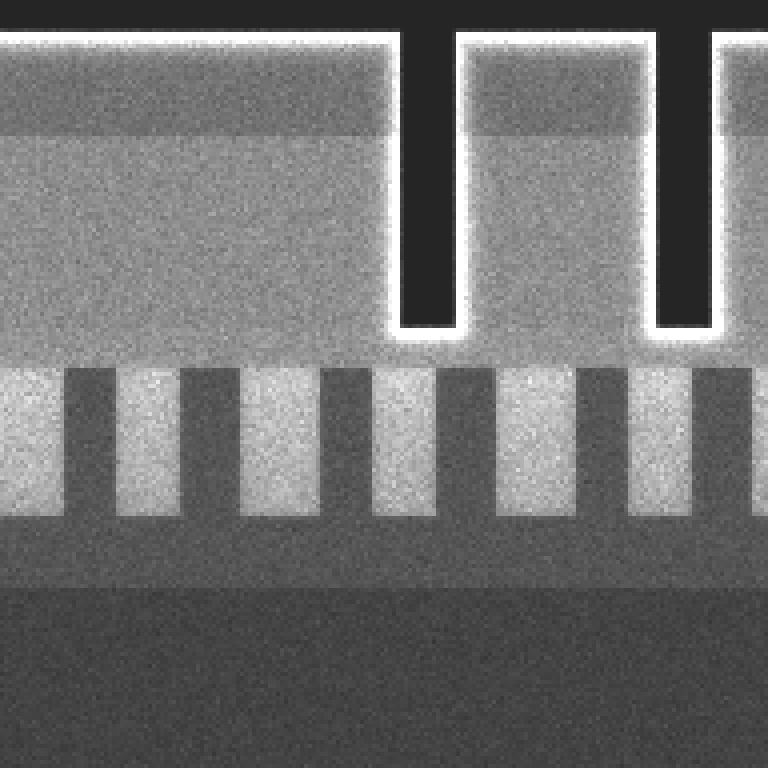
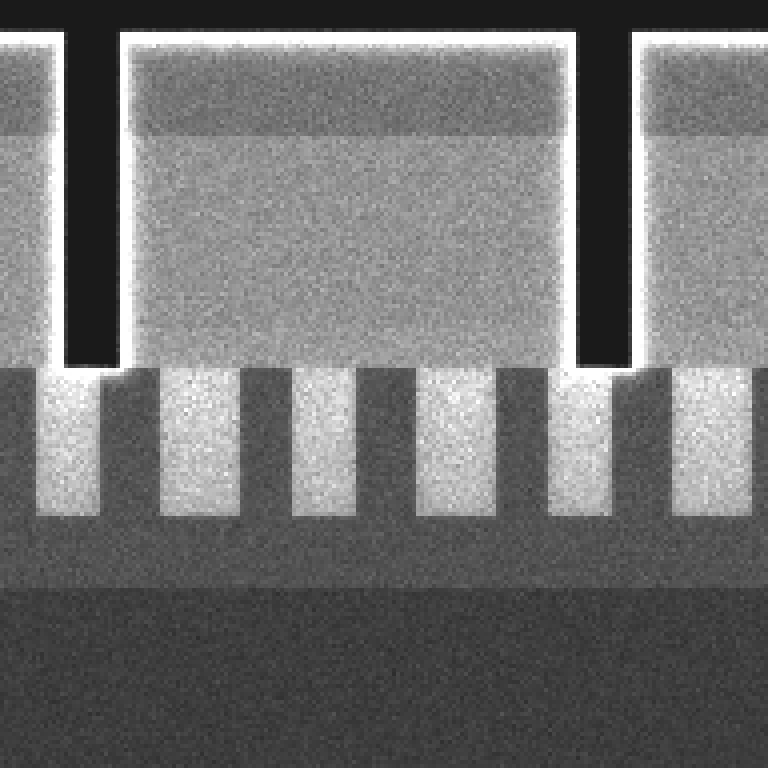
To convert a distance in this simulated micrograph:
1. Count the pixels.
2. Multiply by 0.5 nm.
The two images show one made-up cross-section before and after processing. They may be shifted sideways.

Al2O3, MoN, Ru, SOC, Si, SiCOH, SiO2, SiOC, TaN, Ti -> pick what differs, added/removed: Al2O3 removed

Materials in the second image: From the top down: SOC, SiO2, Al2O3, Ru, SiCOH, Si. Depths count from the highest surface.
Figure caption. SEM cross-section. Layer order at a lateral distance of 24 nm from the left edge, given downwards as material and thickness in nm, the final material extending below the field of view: SOC 52, SiO2 96, Al2O3 20, Ru 74, SiCOH 36, Si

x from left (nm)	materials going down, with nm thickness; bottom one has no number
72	SOC 52, SiO2 96, Al2O3 20, SiCOH 110, Si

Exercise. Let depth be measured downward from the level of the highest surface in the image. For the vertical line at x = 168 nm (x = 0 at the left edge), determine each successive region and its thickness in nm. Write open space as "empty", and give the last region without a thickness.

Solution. SOC 52, SiO2 96, Al2O3 20, Ru 74, SiCOH 36, Si